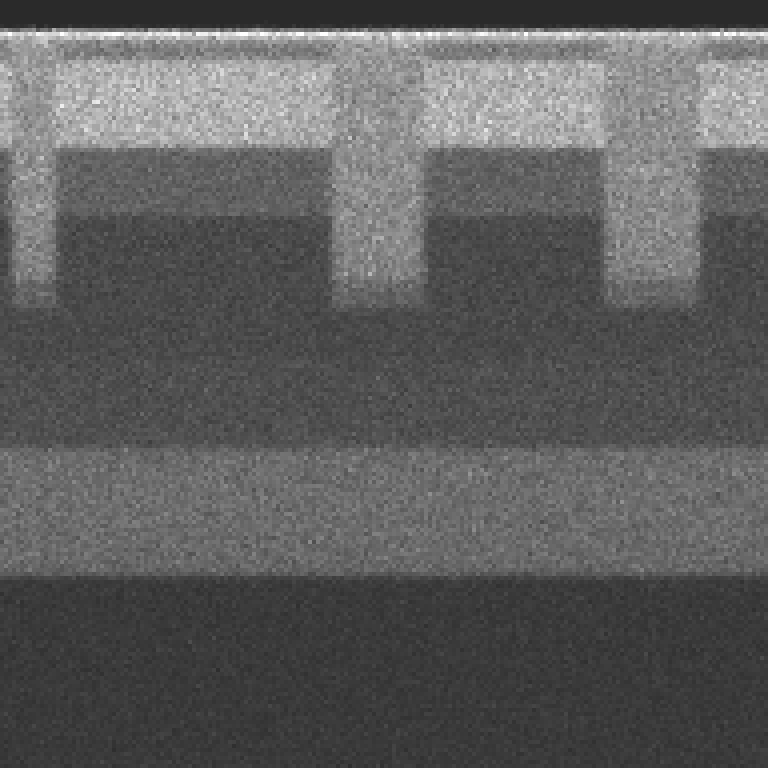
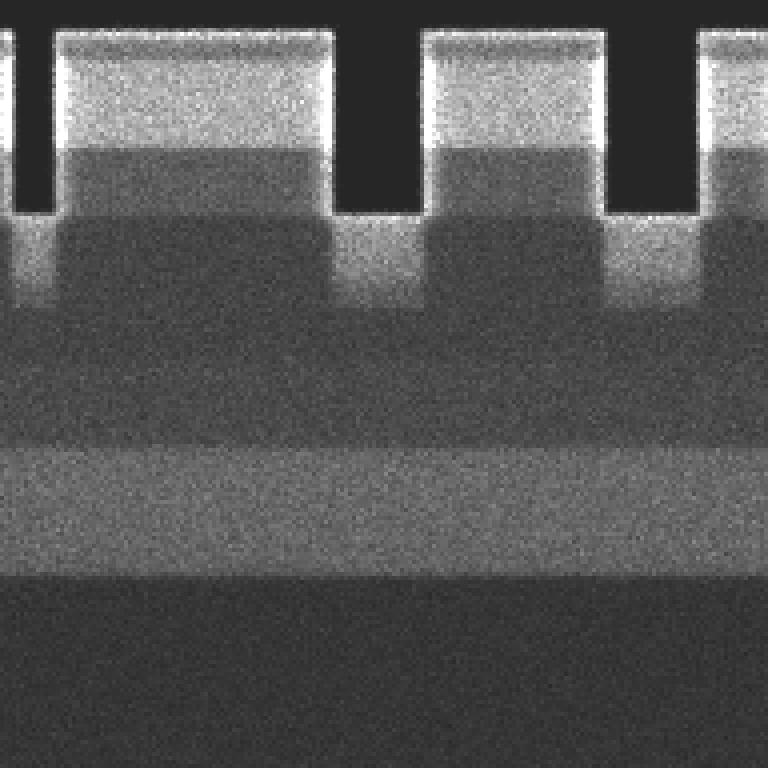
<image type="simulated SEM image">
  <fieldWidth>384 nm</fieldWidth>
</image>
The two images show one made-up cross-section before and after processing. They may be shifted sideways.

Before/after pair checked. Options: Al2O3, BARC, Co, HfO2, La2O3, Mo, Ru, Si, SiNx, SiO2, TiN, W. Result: removed W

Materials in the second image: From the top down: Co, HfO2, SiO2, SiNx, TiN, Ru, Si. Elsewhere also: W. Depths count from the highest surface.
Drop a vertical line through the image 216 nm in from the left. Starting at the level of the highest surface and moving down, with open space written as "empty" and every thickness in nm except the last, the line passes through Co 14, HfO2 44, SiO2 34, SiNx 72, TiN 44, Ru 64, Si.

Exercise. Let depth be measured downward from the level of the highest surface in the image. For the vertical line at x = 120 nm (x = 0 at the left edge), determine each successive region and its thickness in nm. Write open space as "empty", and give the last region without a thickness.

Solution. Co 14, HfO2 44, SiO2 34, SiNx 72, TiN 44, Ru 64, Si